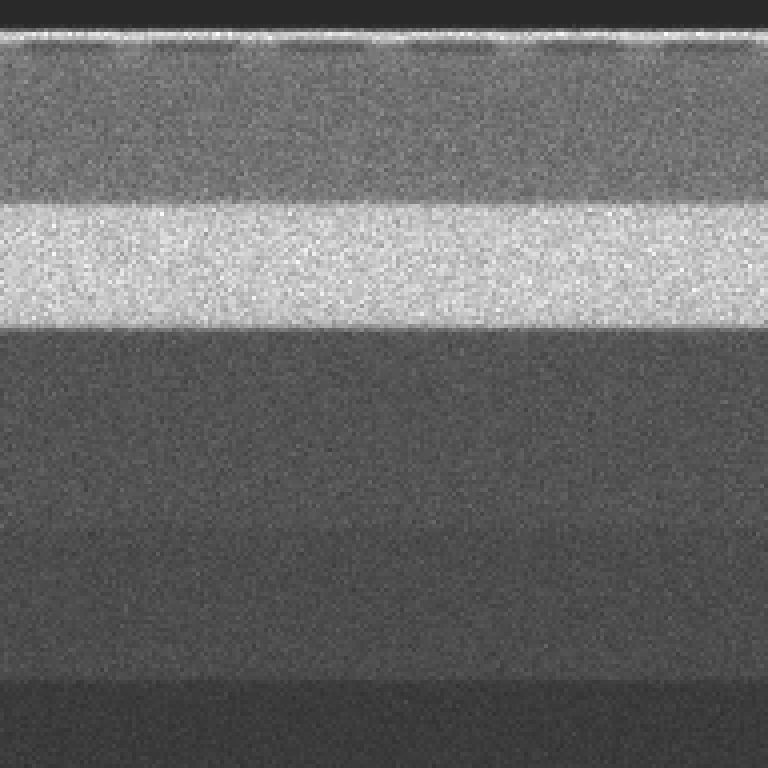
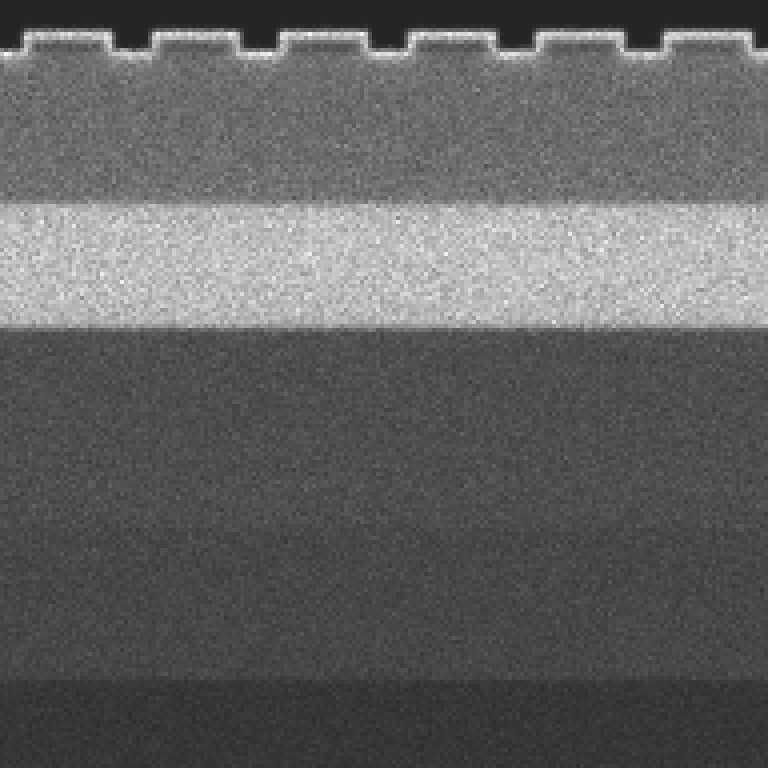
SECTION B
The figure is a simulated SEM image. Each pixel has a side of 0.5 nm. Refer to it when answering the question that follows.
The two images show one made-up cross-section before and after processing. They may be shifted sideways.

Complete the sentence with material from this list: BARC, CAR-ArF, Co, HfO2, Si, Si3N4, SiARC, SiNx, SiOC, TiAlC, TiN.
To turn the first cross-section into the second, SiARC must be removed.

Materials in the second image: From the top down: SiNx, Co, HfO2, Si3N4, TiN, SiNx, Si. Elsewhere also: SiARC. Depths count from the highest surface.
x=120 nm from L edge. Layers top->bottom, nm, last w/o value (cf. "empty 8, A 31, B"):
empty 10, Co 76, HfO2 62, Si3N4 64, TiN 36, SiNx 76, Si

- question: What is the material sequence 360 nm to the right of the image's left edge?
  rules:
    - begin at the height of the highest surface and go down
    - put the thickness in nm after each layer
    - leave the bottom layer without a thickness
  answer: SiNx 10, Co 76, HfO2 62, Si3N4 64, TiN 36, SiNx 76, Si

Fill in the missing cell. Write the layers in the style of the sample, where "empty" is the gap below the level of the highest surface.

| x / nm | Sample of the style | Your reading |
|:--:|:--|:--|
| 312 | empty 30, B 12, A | empty 10, Co 76, HfO2 62, Si3N4 64, TiN 36, SiNx 76, Si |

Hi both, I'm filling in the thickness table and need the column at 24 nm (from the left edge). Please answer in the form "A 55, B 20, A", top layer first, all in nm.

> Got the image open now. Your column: SiNx 10, Co 76, HfO2 62, Si3N4 64, TiN 36, SiNx 76, Si